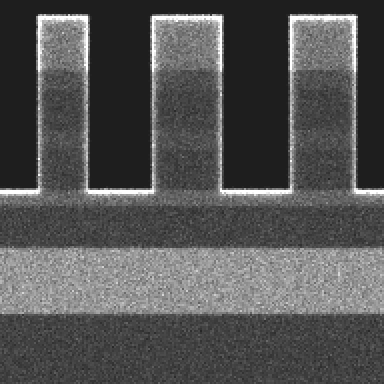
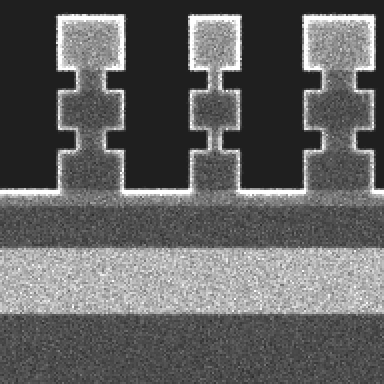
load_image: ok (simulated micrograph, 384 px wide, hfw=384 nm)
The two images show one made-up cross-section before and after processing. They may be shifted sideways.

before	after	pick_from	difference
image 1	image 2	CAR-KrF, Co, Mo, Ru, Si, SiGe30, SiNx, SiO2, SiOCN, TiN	SiGe30 removed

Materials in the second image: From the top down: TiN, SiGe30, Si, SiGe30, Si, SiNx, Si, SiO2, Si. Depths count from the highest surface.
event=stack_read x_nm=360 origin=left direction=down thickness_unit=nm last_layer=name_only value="TiN 54, empty 20, Si 40, empty 20, Si 40, SiNx 16, Si 42, SiO2 66, Si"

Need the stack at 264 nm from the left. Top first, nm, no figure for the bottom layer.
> empty 174, SiNx 16, Si 42, SiO2 66, Si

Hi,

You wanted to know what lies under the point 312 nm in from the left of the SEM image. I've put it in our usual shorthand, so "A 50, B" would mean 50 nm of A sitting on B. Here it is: TiN 54, empty 20, Si 40, empty 20, Si 40, SiNx 16, Si 42, SiO2 66, Si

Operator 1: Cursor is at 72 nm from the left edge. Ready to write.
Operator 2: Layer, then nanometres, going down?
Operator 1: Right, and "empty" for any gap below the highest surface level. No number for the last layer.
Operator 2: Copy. TiN 54, empty 20, Si 40, empty 20, Si 40, SiNx 16, Si 42, SiO2 66, Si